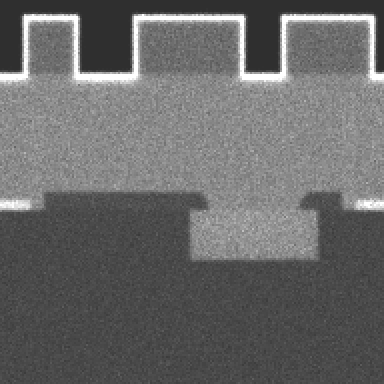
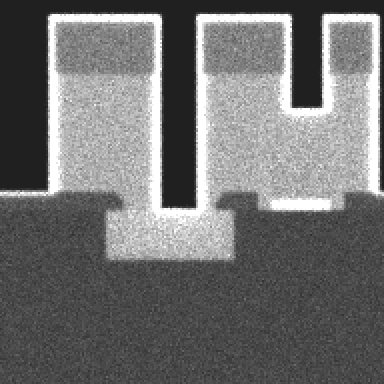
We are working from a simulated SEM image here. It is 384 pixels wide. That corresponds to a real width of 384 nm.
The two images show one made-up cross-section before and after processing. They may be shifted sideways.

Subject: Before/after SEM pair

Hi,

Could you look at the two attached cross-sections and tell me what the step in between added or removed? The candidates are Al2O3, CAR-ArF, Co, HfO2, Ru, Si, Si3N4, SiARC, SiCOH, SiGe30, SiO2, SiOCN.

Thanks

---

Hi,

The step removed SiO2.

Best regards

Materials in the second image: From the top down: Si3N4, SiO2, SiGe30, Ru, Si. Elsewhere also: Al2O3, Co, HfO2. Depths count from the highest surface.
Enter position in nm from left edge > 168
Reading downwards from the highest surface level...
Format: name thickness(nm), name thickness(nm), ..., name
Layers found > empty 194, Ru 50, Si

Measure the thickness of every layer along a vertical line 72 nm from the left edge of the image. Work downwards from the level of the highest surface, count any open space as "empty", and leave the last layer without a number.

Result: Si3N4 58, SiO2 118, SiGe30 18, Si